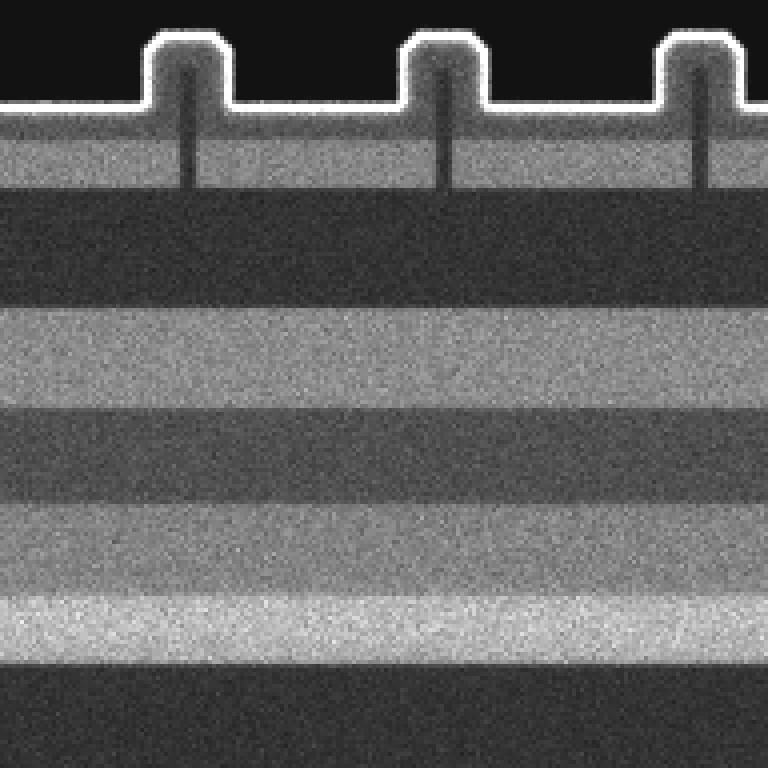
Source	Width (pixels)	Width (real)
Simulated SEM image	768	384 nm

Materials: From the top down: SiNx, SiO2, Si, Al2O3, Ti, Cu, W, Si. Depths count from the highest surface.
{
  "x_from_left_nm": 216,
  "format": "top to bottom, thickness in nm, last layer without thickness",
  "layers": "SiNx 54, SiO2 24, Si 60, Al2O3 50, Ti 48, Cu 46, W 34, Si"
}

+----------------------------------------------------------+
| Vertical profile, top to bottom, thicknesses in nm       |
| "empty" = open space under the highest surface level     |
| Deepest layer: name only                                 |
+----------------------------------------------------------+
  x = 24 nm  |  empty 36, SiNx 18, SiO2 24, Si 60, Al2O3 50, Ti 48, Cu 46, W 34, Si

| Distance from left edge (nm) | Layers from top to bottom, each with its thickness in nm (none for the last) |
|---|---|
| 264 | empty 36, SiNx 18, SiO2 24, Si 60, Al2O3 50, Ti 48, Cu 46, W 34, Si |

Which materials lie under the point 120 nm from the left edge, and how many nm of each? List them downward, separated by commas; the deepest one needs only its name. empty 36, SiNx 18, SiO2 24, Si 60, Al2O3 50, Ti 48, Cu 46, W 34, Si